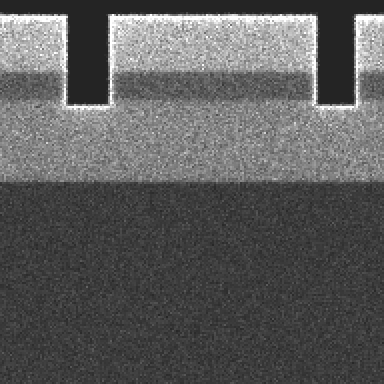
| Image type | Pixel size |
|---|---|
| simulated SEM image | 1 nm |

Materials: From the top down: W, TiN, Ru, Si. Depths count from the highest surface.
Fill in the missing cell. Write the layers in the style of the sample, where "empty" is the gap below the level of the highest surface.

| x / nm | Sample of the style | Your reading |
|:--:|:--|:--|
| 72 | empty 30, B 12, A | empty 90, Ru 76, Si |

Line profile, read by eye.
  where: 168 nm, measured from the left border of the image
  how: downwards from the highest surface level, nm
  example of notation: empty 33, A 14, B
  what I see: W 56, TiN 28, Ru 82, Si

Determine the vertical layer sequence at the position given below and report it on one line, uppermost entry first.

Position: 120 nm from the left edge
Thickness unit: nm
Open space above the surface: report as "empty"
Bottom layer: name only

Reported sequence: W 56, TiN 28, Ru 82, Si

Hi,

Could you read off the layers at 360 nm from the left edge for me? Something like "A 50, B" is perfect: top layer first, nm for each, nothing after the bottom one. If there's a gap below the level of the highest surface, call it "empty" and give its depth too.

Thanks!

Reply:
W 56, TiN 28, Ru 82, Si